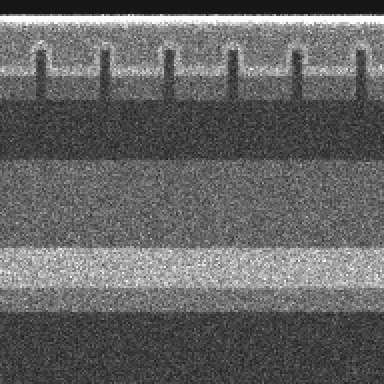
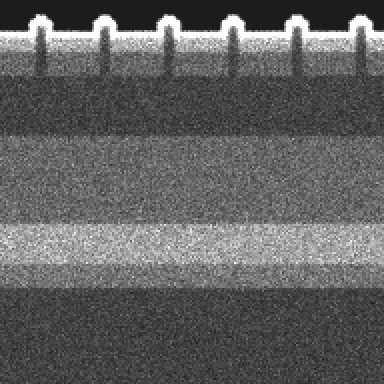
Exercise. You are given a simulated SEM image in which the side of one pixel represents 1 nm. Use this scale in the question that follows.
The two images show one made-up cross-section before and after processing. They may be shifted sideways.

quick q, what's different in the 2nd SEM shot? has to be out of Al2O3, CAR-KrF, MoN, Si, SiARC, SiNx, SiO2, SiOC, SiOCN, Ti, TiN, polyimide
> SiARC removed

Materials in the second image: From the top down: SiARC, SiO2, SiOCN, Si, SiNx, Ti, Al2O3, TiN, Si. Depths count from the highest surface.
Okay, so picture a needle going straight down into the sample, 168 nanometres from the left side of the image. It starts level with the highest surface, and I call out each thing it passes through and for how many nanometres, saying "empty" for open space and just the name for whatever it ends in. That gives SiO2 10, Si 110, SiNx 62, Ti 26, Al2O3 40, TiN 24, Si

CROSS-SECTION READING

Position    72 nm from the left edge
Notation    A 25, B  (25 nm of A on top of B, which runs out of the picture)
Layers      empty 16, SiARC 10, SiO2 10, SiOCN 24, Si 60, SiNx 62, Ti 26, Al2O3 40, TiN 24, Si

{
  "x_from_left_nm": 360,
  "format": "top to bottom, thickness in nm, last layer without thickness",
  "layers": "SiO2 10, Si 110, SiNx 62, Ti 26, Al2O3 40, TiN 24, Si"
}